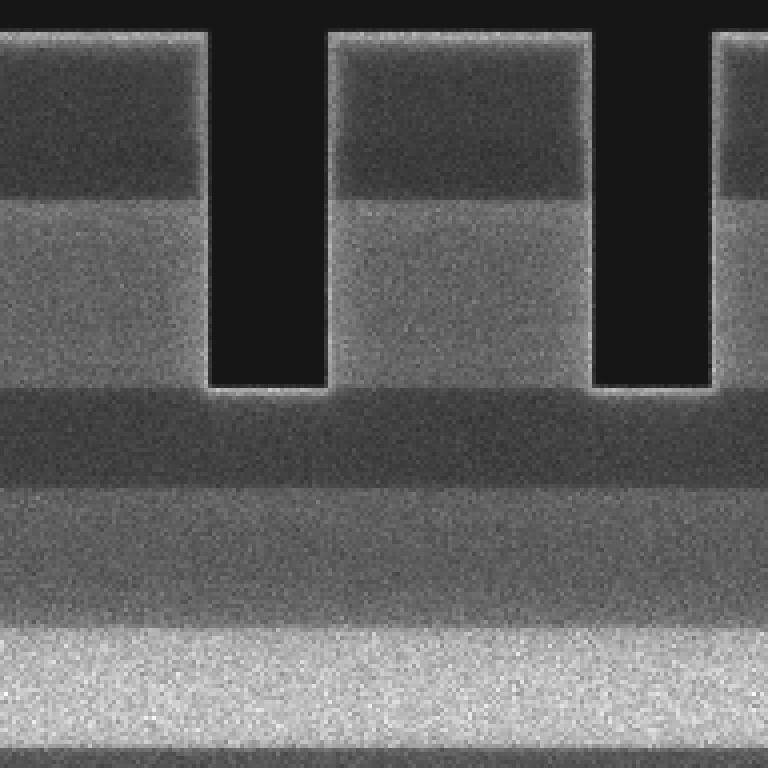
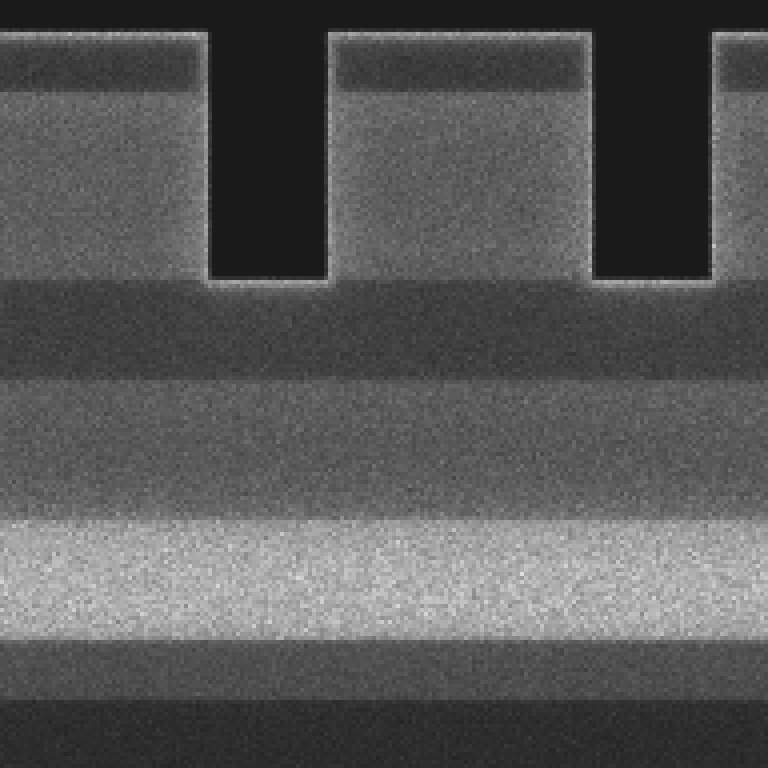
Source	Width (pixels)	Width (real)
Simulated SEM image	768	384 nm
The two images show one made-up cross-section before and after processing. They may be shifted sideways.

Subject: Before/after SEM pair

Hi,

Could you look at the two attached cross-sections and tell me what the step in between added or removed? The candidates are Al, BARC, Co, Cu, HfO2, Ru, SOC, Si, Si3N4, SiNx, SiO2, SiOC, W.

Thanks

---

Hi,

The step removed SOC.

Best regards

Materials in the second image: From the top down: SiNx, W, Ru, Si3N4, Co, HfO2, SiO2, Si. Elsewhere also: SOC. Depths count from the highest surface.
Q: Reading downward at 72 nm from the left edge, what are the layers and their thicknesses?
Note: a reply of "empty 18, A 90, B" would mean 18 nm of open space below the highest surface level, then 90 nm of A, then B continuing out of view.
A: SiNx 30, W 82, Ru 12, Si3N4 50, Co 70, HfO2 60, SiO2 30, Si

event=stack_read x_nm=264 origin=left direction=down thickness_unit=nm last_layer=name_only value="SiNx 30, W 82, Ru 12, Si3N4 50, Co 70, HfO2 60, SiO2 30, Si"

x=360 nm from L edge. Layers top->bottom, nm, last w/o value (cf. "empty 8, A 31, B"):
SiNx 30, W 82, Ru 12, Si3N4 50, Co 70, HfO2 60, SiO2 30, Si